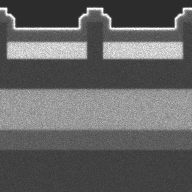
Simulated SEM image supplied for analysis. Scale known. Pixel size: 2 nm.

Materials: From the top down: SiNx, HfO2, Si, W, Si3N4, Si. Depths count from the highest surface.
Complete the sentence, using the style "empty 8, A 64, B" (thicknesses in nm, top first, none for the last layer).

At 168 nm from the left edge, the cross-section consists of empty 12, SiNx 56, HfO2 34, Si 60, W 82, Si3N4 40, Si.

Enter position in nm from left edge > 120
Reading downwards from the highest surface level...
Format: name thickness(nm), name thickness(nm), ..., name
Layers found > empty 40, SiNx 28, HfO2 34, Si 60, W 82, Si3N4 40, Si